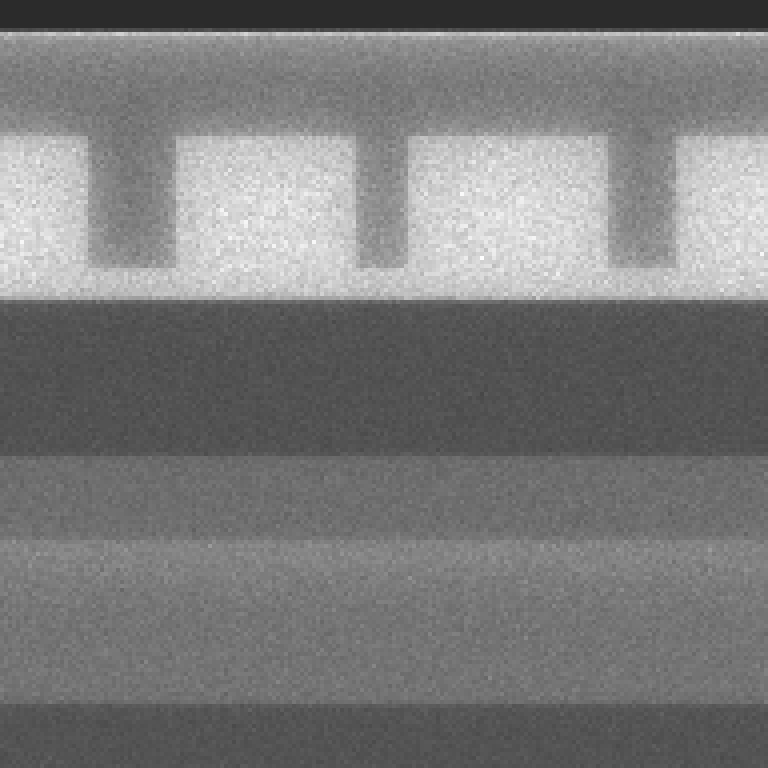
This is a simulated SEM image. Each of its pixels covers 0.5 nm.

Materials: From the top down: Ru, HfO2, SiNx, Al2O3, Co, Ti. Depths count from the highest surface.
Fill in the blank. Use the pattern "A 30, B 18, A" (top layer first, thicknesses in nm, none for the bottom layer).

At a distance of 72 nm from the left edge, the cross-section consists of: Ru 118, HfO2 16, SiNx 78, Al2O3 42, Co 82, Ti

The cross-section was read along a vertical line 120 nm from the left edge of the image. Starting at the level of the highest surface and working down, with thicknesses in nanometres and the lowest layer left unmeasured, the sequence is Ru 52, HfO2 82, SiNx 78, Al2O3 42, Co 82, Ti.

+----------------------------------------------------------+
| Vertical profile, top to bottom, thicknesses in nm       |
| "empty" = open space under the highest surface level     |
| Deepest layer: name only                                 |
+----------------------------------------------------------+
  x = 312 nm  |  Ru 118, HfO2 16, SiNx 78, Al2O3 42, Co 82, Ti